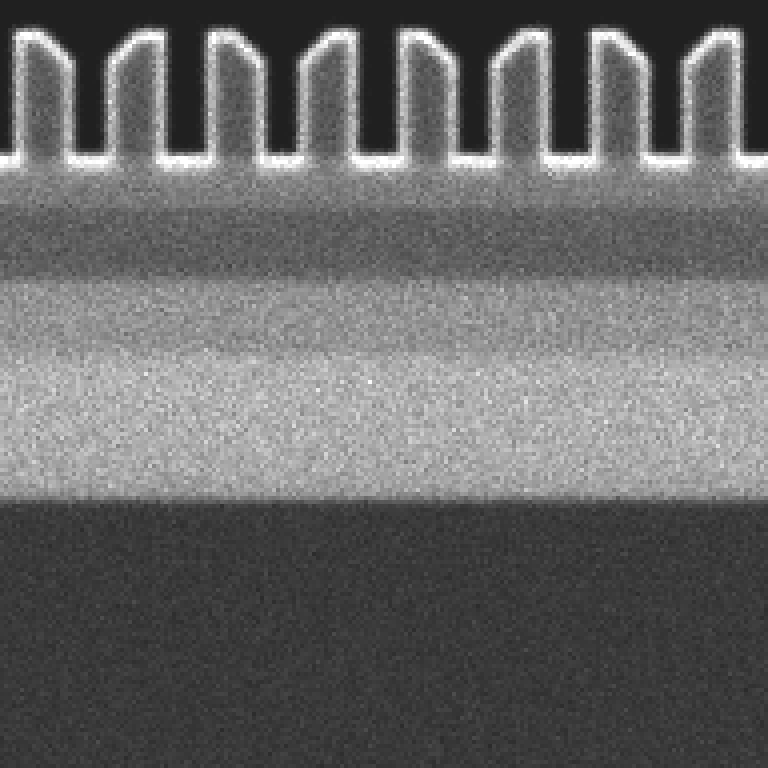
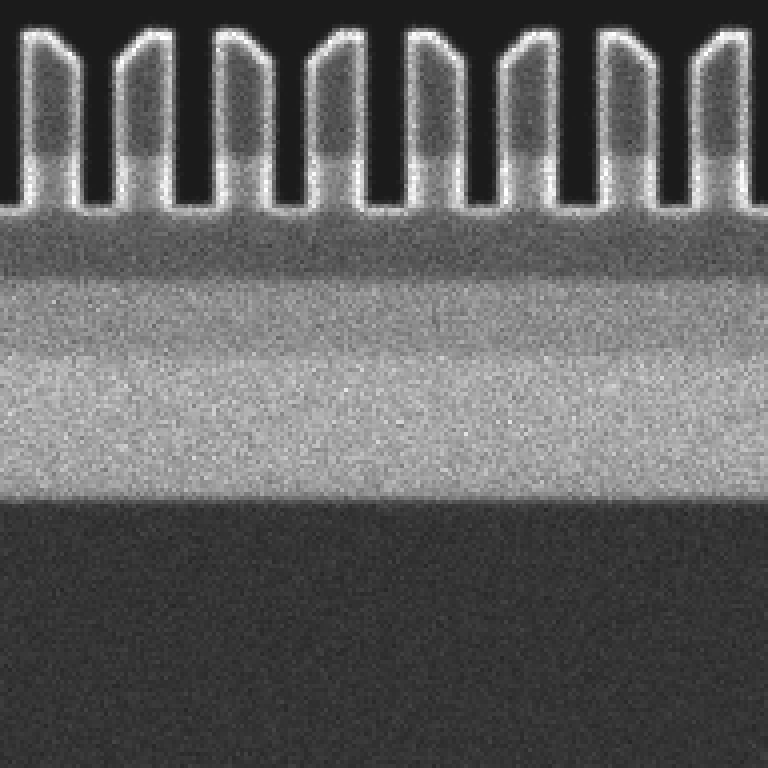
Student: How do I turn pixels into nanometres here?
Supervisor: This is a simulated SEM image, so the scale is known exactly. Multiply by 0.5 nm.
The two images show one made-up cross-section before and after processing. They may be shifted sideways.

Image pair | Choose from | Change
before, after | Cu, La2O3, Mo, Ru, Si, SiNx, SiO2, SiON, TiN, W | SiO2 (removed)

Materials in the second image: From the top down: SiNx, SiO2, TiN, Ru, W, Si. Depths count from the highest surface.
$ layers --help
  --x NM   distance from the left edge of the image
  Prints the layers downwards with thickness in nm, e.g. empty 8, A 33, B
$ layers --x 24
SiNx 62, SiO2 26, TiN 36, Ru 38, W 72, Si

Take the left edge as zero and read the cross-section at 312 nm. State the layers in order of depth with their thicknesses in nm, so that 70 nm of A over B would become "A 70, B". SiNx 62, SiO2 26, TiN 36, Ru 38, W 72, Si